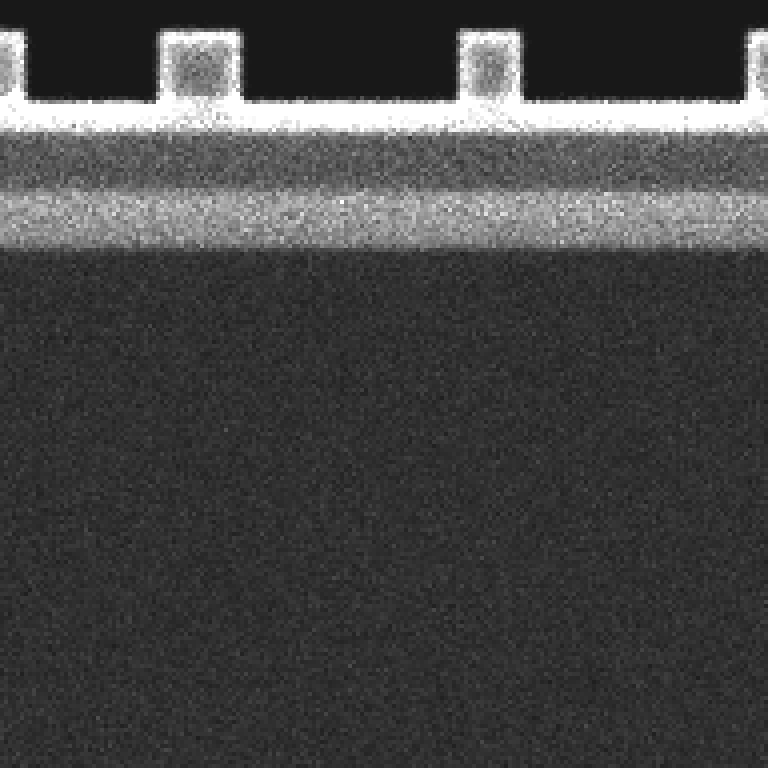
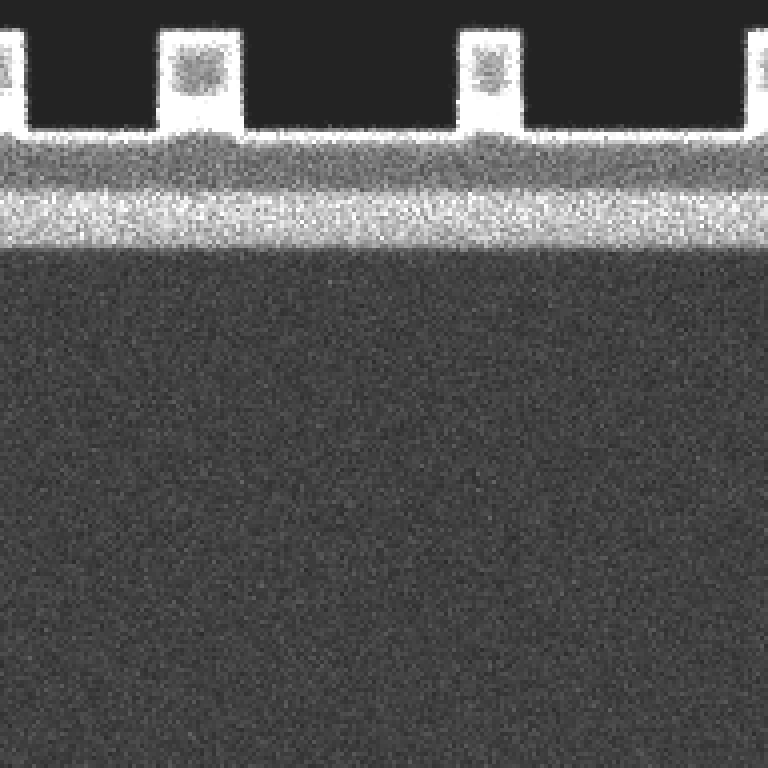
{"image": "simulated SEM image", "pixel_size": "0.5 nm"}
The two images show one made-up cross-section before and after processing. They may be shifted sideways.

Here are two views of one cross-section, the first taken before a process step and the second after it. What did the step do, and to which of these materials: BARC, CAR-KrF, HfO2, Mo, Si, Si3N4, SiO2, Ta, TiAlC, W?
It removed HfO2.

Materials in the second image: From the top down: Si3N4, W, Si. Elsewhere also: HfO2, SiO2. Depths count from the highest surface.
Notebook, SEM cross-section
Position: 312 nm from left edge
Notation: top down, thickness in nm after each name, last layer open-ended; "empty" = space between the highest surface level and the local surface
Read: empty 50, Si3N4 30, W 28, Si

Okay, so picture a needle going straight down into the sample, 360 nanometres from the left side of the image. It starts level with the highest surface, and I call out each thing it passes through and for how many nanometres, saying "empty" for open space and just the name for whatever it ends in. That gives empty 50, Si3N4 30, W 28, Si